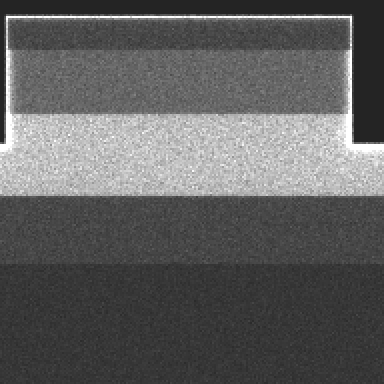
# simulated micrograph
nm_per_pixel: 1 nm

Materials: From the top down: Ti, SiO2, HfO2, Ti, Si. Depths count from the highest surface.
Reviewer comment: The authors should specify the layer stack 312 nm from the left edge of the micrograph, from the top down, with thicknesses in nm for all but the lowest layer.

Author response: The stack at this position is Ti 34, SiO2 64, HfO2 82, Ti 68, Si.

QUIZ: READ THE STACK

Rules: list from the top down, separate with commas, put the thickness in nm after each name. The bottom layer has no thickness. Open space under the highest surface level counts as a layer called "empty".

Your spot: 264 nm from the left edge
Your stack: Ti 34, SiO2 64, HfO2 82, Ti 68, Si